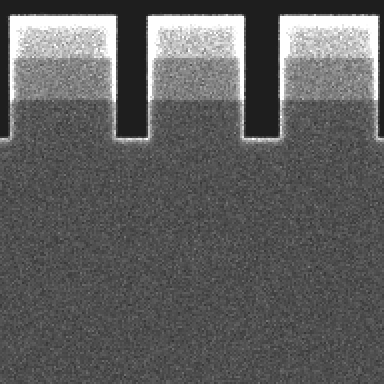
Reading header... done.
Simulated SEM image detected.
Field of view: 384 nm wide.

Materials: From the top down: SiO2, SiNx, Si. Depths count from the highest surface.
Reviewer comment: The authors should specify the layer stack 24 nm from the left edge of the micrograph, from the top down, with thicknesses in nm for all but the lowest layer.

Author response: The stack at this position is SiO2 42, SiNx 42, Si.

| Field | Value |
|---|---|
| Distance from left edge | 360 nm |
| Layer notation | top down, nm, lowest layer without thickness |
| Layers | SiO2 42, SiNx 42, Si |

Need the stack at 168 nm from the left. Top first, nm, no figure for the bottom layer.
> SiO2 42, SiNx 42, Si